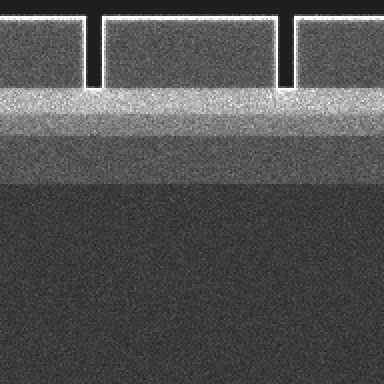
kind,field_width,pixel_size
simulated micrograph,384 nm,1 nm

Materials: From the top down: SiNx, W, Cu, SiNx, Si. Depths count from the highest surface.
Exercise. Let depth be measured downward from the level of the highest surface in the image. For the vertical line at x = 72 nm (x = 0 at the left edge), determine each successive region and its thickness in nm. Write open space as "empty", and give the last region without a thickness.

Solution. SiNx 72, W 26, Cu 22, SiNx 48, Si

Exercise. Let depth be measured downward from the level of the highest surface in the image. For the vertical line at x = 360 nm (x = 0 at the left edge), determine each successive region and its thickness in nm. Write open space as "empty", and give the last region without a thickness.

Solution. SiNx 72, W 26, Cu 22, SiNx 48, Si